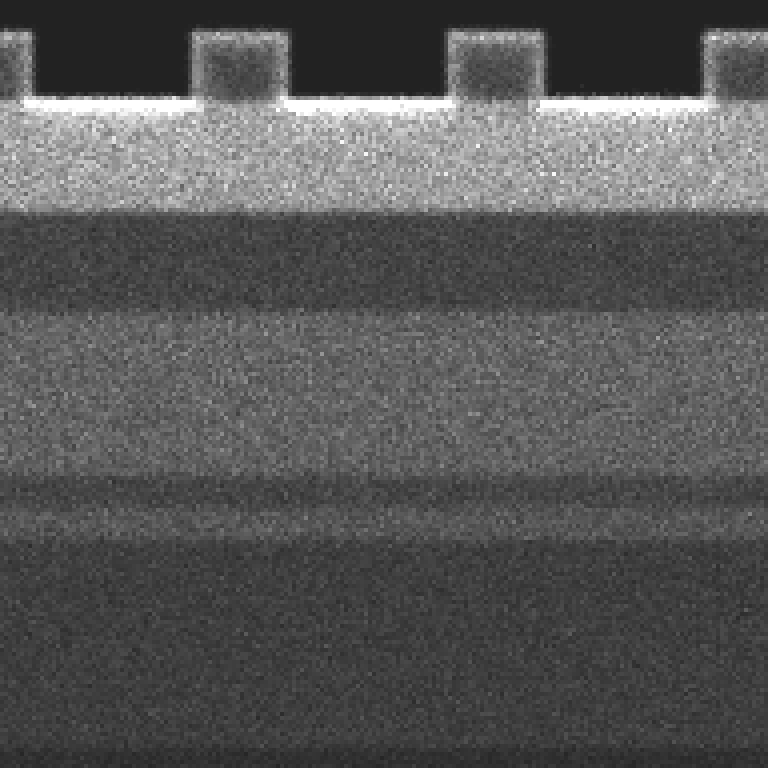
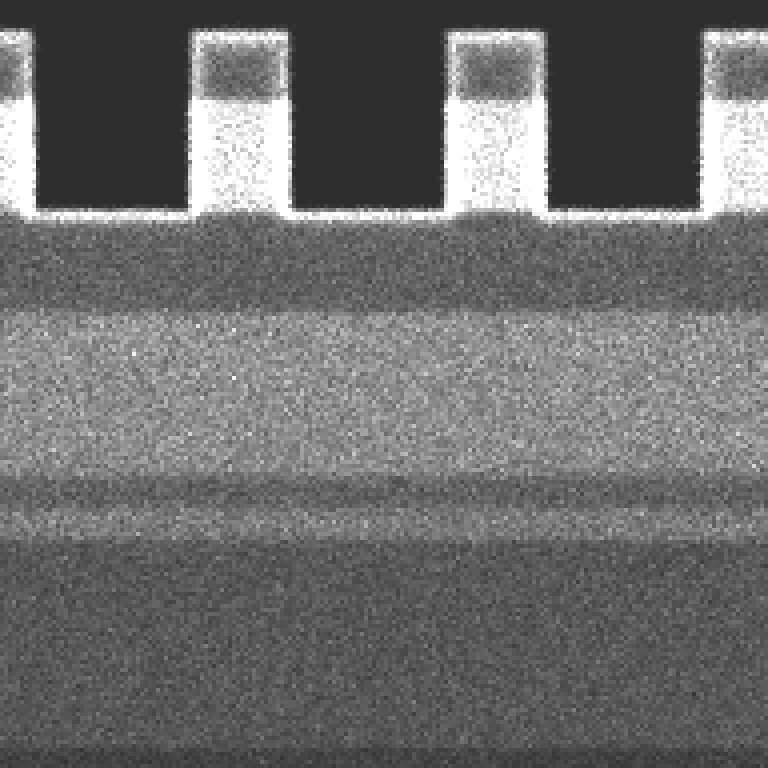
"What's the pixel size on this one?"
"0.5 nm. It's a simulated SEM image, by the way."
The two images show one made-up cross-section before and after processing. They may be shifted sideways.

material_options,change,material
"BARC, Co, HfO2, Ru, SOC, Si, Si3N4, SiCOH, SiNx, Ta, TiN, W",removed,HfO2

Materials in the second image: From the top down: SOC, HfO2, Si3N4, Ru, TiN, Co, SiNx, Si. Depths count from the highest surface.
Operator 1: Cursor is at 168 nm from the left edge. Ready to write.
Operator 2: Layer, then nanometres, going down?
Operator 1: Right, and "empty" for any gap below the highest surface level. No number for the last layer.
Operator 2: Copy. empty 90, Si3N4 50, Ru 82, TiN 16, Co 16, SiNx 104, Si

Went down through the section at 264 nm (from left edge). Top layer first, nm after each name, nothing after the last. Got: SOC 34, HfO2 56, Si3N4 50, Ru 82, TiN 16, Co 16, SiNx 104, Si